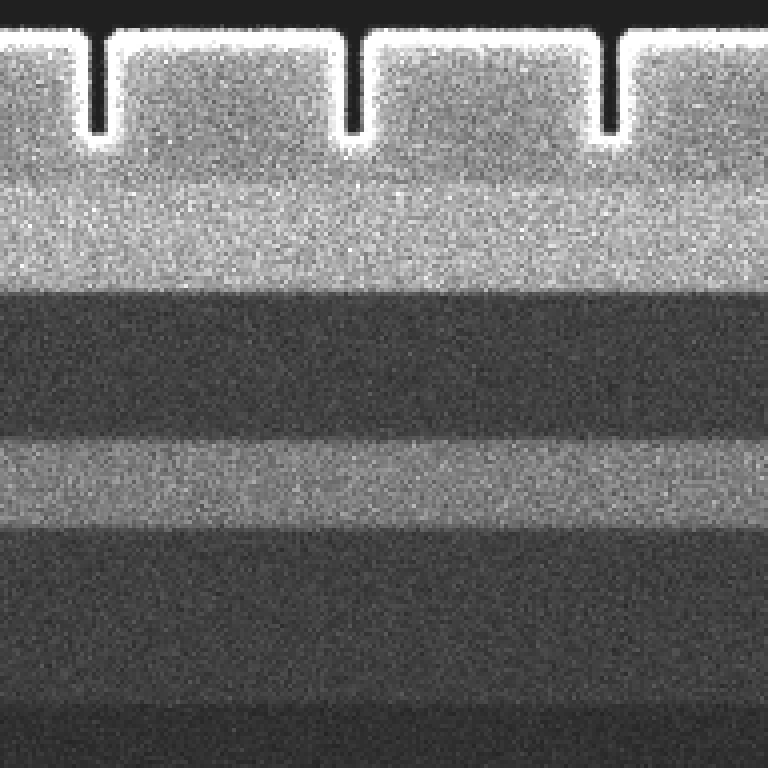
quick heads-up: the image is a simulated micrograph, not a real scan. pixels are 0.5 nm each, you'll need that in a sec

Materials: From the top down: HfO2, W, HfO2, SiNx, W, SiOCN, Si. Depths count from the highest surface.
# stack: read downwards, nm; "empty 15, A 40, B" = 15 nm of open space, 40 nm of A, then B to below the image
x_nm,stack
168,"empty 2, HfO2 58, W 16, HfO2 54, SiNx 74, W 44, SiOCN 88, Si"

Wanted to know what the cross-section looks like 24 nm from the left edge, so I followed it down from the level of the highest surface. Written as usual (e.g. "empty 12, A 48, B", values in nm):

HfO2 8, W 68, HfO2 54, SiNx 74, W 44, SiOCN 88, Si